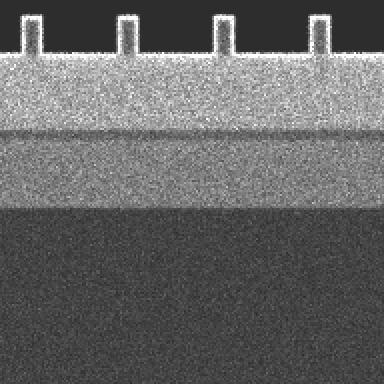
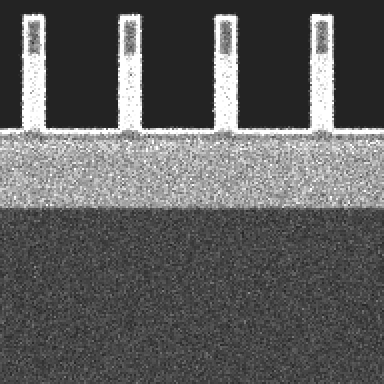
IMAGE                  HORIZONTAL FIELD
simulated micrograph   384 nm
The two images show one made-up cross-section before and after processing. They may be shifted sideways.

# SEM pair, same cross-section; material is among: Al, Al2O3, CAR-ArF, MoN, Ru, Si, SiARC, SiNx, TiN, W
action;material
removed;W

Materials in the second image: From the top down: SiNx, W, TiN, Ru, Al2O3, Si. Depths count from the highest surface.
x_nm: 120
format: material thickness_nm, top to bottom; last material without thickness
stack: SiNx 38, W 76, TiN 10, Ru 12, Al2O3 56, Si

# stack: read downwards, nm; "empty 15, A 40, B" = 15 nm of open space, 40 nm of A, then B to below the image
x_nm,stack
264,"empty 114, TiN 10, Ru 12, Al2O3 56, Si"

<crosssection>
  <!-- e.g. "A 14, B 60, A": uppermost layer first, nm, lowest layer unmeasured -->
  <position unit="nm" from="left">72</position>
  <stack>empty 114, TiN 10, Ru 12, Al2O3 56, Si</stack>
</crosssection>